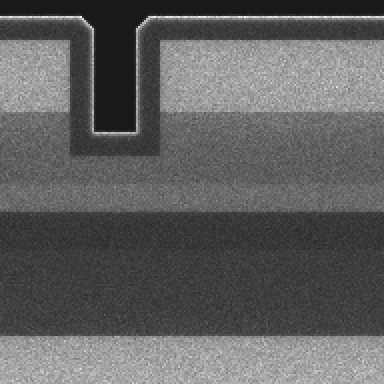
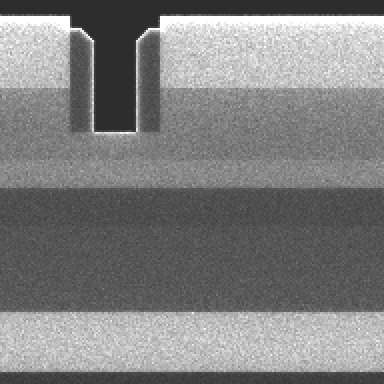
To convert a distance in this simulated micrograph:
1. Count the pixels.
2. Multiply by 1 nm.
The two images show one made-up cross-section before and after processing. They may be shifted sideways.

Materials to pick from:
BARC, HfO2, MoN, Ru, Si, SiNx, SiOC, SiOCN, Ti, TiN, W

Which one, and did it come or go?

SiNx - removed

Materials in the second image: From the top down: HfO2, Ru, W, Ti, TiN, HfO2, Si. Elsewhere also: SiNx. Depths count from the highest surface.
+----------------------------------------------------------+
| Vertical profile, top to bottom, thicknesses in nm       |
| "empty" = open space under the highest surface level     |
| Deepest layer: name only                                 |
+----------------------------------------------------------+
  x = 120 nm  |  empty 116, Ru 28, W 28, Ti 38, TiN 86, HfO2 60, Si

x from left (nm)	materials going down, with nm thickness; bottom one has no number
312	HfO2 72, Ru 72, W 28, Ti 38, TiN 86, HfO2 60, Si